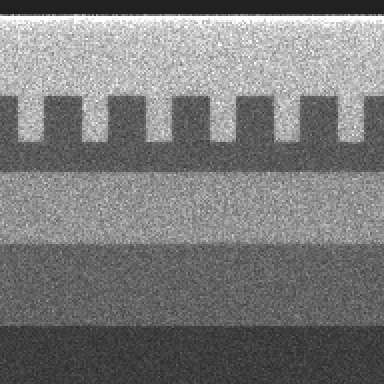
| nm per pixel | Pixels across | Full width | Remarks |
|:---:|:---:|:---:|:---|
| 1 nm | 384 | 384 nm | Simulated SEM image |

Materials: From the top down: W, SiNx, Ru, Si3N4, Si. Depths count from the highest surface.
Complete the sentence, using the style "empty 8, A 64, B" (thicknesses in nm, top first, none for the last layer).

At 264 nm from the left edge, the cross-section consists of W 80, SiNx 76, Ru 72, Si3N4 82, Si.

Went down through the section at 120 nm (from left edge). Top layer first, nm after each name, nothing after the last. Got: W 80, SiNx 76, Ru 72, Si3N4 82, Si